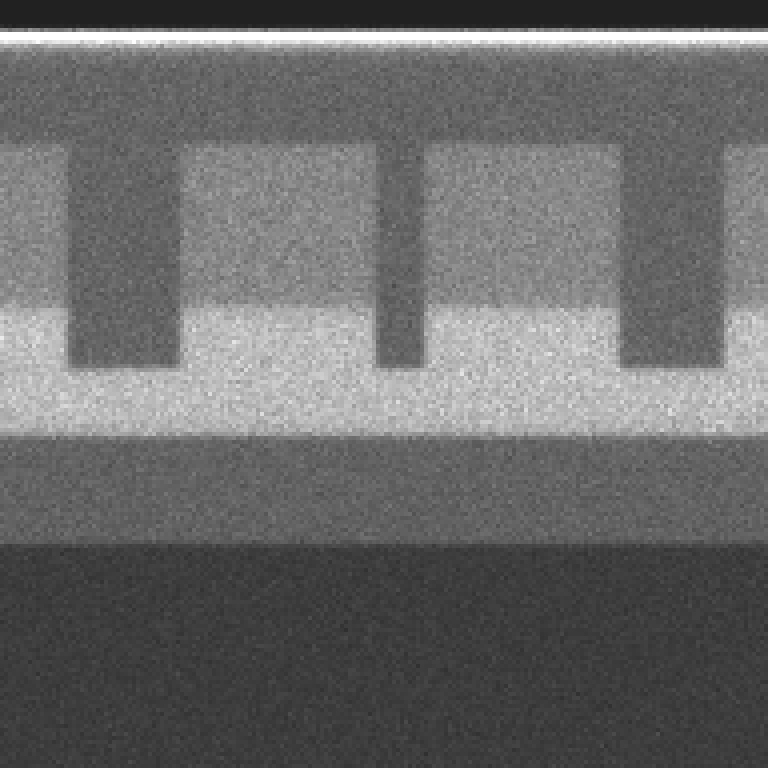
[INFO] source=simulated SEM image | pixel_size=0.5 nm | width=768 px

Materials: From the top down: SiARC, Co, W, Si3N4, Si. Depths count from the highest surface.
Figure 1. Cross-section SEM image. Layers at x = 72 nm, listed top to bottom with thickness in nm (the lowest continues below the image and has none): SiARC 168, W 34, Si3N4 54, Si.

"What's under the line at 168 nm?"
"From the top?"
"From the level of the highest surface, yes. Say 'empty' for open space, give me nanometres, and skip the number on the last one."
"SiARC 56, Co 82, W 64, Si3N4 54, Si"